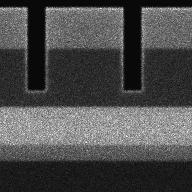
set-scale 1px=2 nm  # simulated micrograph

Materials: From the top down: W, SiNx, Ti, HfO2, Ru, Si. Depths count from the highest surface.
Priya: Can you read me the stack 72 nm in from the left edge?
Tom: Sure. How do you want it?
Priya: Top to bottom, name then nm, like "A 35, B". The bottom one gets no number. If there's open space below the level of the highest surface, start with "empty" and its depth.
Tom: empty 166, Ti 32, HfO2 76, Ru 32, Si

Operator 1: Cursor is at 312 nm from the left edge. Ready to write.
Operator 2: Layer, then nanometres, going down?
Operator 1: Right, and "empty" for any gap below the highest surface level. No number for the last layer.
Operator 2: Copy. W 82, SiNx 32, Ti 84, HfO2 76, Ru 32, Si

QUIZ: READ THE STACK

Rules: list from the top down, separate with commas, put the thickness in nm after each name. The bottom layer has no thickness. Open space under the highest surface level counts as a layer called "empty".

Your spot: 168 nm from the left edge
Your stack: W 82, SiNx 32, Ti 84, HfO2 76, Ru 32, Si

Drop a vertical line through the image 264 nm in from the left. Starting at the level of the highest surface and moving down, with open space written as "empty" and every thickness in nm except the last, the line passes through empty 166, Ti 32, HfO2 76, Ru 32, Si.